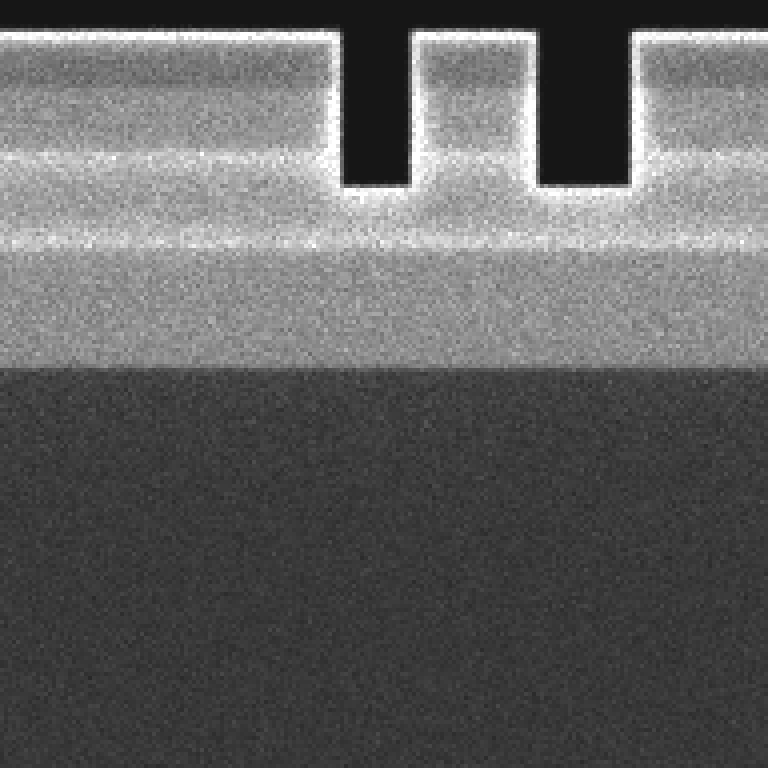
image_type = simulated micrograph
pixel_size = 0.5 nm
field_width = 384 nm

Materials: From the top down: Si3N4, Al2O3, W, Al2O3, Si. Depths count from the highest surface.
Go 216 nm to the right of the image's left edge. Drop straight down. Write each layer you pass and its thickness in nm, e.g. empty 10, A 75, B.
Si3N4 28, Al2O3 32, W 48, Al2O3 60, Si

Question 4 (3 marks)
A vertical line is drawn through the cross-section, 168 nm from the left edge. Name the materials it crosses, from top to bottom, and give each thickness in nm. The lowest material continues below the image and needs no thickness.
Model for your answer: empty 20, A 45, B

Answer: Si3N4 28, Al2O3 32, W 48, Al2O3 60, Si